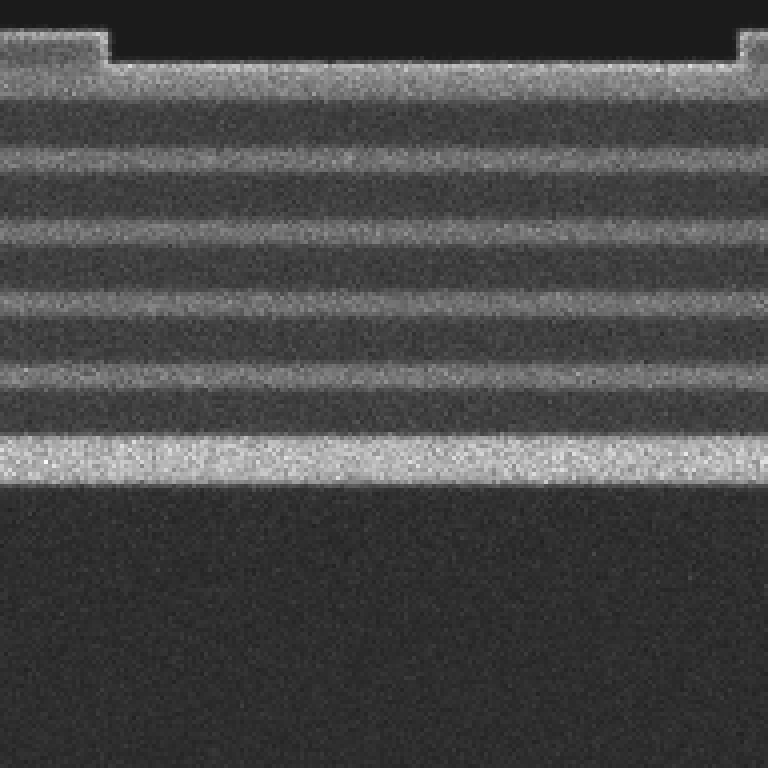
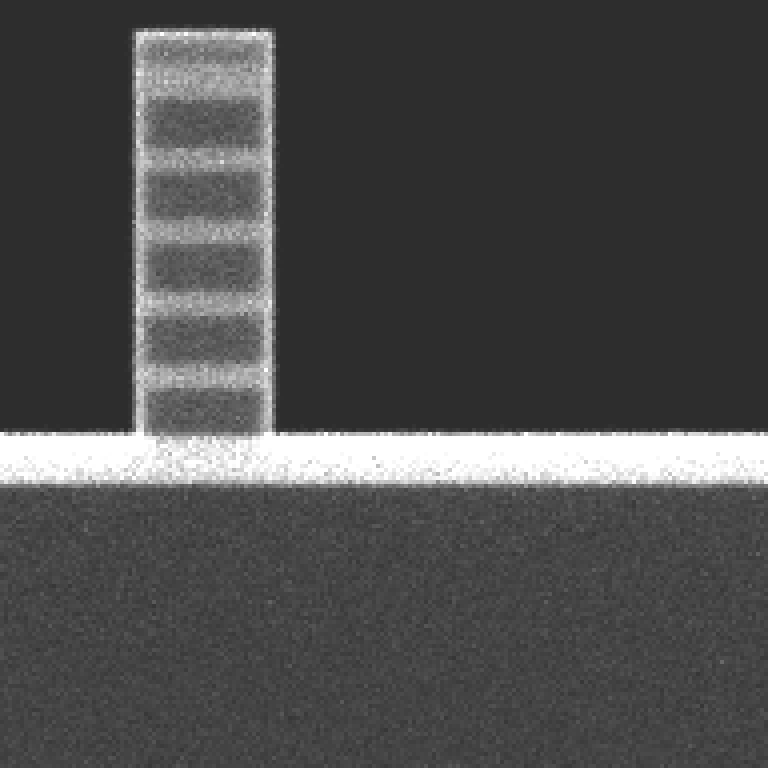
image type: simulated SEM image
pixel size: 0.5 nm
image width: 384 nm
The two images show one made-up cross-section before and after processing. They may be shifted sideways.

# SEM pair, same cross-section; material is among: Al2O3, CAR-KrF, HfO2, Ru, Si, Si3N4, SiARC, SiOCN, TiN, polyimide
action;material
removed;Ru and SiOCN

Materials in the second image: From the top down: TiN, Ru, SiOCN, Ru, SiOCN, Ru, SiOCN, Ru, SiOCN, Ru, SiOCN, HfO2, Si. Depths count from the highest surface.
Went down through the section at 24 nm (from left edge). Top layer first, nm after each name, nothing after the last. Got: empty 202, HfO2 24, Si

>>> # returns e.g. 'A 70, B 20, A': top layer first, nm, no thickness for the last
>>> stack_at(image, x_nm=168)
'empty 202, HfO2 24, Si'